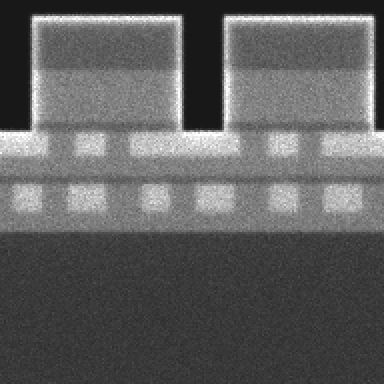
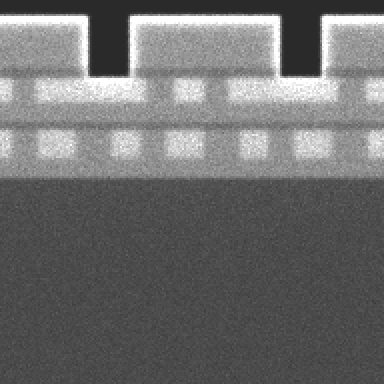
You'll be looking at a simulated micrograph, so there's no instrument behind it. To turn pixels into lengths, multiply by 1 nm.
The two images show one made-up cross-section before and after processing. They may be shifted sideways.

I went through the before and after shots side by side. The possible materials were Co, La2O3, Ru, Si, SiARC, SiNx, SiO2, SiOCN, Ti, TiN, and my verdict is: removed, SiARC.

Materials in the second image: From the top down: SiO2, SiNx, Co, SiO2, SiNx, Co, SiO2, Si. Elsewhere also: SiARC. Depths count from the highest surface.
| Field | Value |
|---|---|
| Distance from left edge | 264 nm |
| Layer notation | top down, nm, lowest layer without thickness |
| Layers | SiO2 52, SiNx 10, Co 24, SiO2 20, SiNx 8, Co 28, SiO2 20, Si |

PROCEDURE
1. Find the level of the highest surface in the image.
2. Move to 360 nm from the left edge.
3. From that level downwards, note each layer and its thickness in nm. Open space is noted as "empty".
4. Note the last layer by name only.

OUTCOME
SiO2 52, SiNx 10, SiO2 44, SiNx 8, SiO2 48, Si